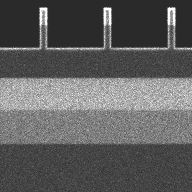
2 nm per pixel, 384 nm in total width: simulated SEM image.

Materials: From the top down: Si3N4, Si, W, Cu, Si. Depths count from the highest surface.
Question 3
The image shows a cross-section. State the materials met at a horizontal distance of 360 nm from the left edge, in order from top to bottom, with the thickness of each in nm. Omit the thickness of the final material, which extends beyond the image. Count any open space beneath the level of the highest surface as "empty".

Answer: empty 80, Si 60, W 64, Cu 68, Si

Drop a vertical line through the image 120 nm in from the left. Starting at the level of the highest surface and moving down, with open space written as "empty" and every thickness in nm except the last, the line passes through empty 80, Si 60, W 64, Cu 68, Si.